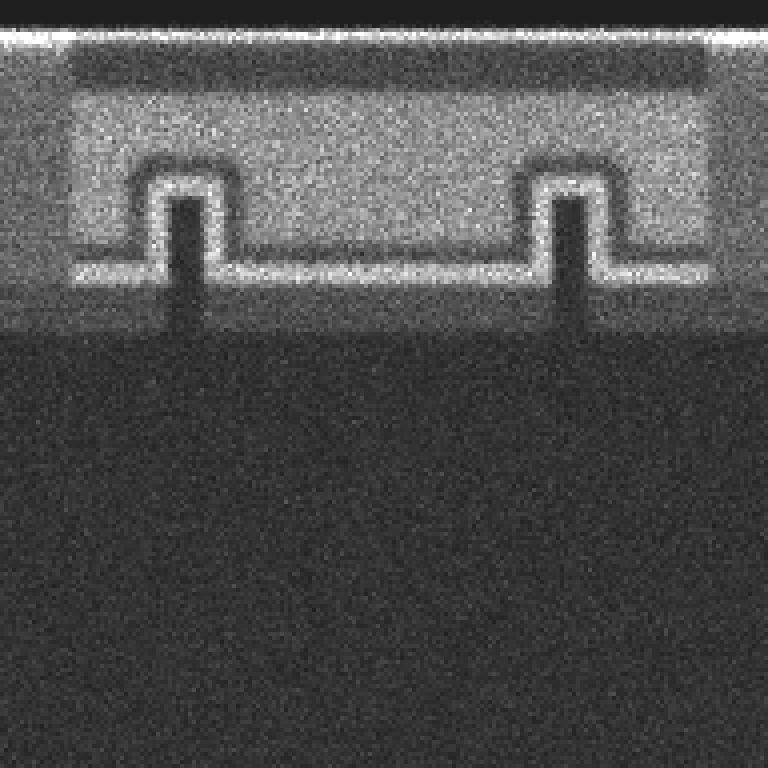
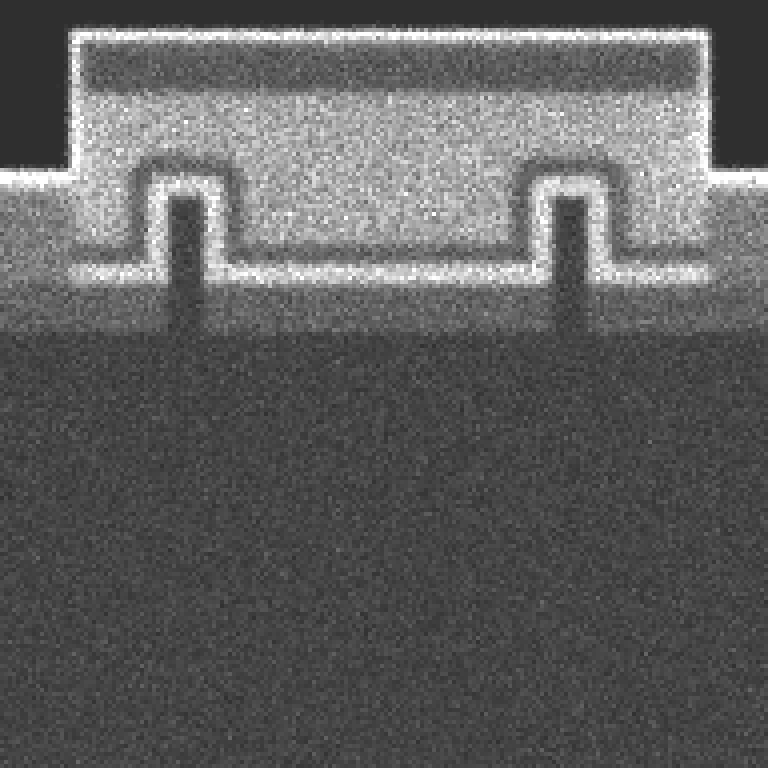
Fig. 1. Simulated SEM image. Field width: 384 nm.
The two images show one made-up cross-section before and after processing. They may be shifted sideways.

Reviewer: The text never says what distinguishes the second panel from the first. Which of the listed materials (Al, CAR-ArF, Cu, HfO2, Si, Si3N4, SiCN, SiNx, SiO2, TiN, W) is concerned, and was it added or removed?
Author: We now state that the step removed SiO2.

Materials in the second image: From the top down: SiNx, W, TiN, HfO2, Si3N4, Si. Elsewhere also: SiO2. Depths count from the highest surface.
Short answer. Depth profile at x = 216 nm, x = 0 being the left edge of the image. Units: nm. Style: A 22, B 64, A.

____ SiNx 30, W 76, TiN 10, HfO2 10, Si3N4 24, Si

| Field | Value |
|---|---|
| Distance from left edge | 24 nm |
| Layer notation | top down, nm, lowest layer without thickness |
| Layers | empty 70, SiO2 56, Si3N4 24, Si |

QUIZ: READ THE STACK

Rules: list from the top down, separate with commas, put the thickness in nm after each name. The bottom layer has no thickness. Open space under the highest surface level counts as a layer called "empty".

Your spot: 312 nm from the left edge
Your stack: SiNx 30, W 40, TiN 46, HfO2 10, Si3N4 24, Si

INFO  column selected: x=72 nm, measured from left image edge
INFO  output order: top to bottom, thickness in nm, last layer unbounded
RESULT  SiNx 30, W 32, TiN 54, HfO2 10, Si3N4 24, Si